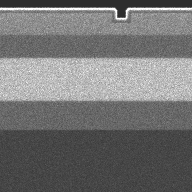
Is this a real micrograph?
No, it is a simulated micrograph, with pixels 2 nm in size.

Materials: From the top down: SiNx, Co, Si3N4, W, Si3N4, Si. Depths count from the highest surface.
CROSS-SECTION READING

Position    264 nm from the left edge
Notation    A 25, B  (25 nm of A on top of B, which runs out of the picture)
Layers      SiNx 10, Co 44, Si3N4 46, W 86, Si3N4 58, Si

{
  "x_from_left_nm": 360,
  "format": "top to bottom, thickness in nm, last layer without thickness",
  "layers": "SiNx 10, Co 44, Si3N4 46, W 86, Si3N4 58, Si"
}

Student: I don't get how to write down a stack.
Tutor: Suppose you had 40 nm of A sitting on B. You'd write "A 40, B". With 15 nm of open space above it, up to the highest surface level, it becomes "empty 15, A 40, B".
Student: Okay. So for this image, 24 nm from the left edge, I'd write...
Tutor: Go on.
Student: SiNx 10, Co 44, Si3N4 46, W 86, Si3N4 58, Si